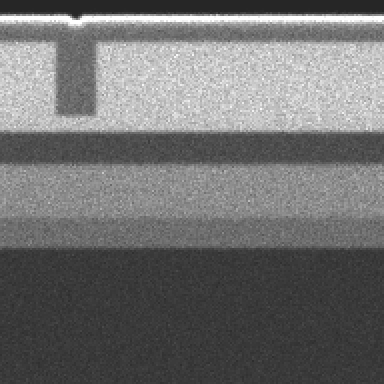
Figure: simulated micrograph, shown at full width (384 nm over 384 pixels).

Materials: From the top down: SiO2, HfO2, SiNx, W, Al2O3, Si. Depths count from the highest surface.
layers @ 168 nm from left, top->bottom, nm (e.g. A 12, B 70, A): SiO2 26, HfO2 90, SiNx 32, W 54, Al2O3 30, Si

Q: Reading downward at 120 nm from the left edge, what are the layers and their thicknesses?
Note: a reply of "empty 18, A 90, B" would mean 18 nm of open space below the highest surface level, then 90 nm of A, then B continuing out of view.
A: SiO2 26, HfO2 90, SiNx 32, W 54, Al2O3 30, Si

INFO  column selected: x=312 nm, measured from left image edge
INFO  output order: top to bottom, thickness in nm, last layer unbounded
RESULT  SiO2 26, HfO2 90, SiNx 32, W 54, Al2O3 30, Si